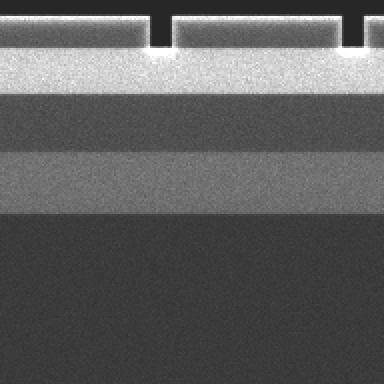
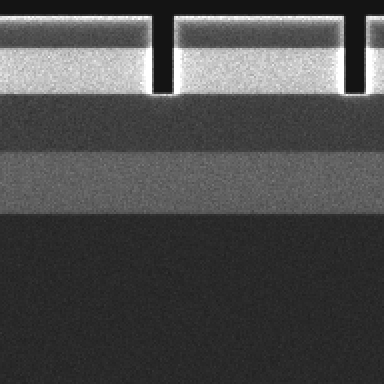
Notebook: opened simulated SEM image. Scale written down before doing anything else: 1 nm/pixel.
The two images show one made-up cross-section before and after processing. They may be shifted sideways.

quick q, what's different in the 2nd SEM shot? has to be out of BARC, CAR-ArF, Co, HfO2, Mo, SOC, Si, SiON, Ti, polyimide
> HfO2 removed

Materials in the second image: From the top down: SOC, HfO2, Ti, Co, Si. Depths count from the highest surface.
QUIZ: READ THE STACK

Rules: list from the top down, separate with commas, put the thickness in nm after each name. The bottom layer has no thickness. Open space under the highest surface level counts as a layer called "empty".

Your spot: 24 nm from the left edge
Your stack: SOC 32, HfO2 46, Ti 58, Co 62, Si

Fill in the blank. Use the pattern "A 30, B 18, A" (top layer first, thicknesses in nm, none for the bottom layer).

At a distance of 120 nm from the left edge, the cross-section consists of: SOC 32, HfO2 46, Ti 58, Co 62, Si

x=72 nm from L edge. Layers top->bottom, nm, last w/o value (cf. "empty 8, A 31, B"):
SOC 32, HfO2 46, Ti 58, Co 62, Si